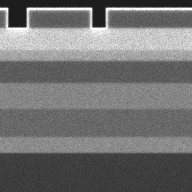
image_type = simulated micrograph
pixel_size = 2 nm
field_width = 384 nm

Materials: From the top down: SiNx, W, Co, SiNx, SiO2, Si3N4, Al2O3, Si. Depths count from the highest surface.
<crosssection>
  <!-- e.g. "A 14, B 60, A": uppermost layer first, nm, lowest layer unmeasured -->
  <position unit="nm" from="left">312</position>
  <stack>SiNx 40, W 44, Co 22, SiNx 44, SiO2 52, Si3N4 56, Al2O3 32, Si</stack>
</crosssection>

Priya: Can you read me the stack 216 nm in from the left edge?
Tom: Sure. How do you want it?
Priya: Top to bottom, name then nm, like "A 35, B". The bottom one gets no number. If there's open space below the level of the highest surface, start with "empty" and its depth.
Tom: SiNx 40, W 44, Co 22, SiNx 44, SiO2 52, Si3N4 56, Al2O3 32, Si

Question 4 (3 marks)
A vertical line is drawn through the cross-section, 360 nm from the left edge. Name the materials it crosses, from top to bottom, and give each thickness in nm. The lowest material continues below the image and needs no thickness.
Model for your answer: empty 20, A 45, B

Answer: SiNx 40, W 44, Co 22, SiNx 44, SiO2 52, Si3N4 56, Al2O3 32, Si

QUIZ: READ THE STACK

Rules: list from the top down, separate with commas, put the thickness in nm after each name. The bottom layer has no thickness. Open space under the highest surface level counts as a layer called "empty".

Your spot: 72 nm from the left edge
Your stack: SiNx 40, W 44, Co 22, SiNx 44, SiO2 52, Si3N4 56, Al2O3 32, Si